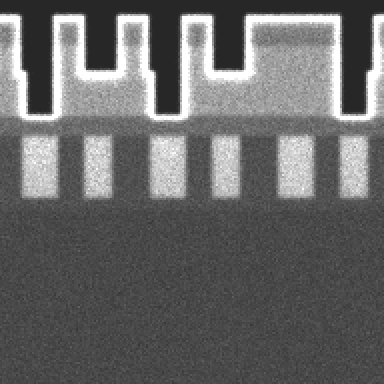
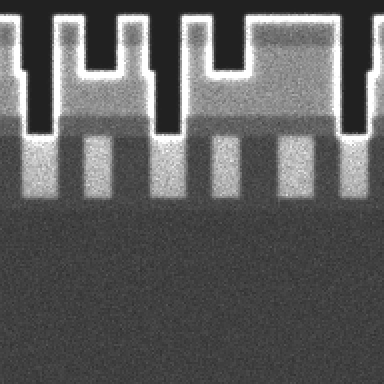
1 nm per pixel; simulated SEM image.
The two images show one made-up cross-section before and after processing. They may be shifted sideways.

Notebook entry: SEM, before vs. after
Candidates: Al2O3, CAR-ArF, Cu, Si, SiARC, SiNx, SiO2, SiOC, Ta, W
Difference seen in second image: SiNx removed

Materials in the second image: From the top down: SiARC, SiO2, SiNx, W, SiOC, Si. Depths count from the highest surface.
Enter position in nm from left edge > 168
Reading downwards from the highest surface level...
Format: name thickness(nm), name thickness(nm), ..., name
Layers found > empty 120, W 62, SiOC 12, Si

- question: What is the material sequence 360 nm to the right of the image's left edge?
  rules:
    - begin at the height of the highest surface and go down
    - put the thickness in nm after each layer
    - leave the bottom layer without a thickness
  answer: empty 120, W 62, SiOC 12, Si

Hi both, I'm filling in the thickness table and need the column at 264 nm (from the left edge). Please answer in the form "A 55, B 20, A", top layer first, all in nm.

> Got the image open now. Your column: SiARC 30, SiO2 70, SiNx 20, SiOC 74, Si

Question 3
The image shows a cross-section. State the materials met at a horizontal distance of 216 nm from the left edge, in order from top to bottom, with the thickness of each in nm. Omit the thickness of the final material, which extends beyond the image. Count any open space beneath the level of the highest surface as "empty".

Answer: empty 56, SiO2 44, SiNx 20, W 62, SiOC 12, Si